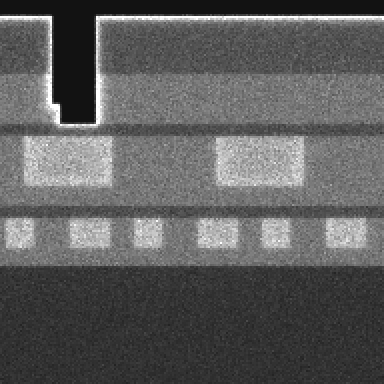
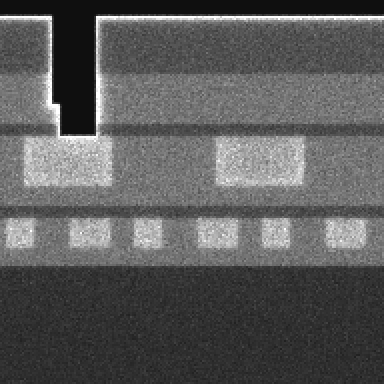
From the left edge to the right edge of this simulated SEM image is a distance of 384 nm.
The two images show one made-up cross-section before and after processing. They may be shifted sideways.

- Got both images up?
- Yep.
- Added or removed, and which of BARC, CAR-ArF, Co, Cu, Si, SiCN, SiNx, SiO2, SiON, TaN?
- removed, SiCN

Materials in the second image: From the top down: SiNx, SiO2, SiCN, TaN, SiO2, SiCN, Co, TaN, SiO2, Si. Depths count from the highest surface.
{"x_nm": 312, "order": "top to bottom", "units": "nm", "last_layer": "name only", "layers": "SiNx 58, SiO2 50, SiCN 12, SiO2 70, SiCN 12, SiO2 48, Si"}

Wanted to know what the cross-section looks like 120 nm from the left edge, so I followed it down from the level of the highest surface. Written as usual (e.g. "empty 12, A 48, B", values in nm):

SiNx 58, SiO2 50, SiCN 12, SiO2 70, SiCN 12, SiO2 48, Si